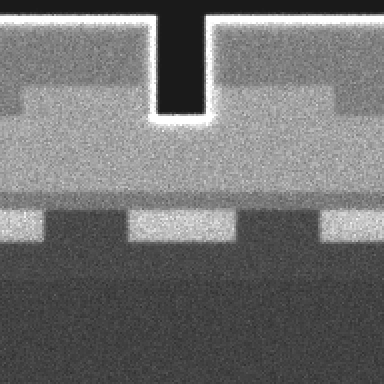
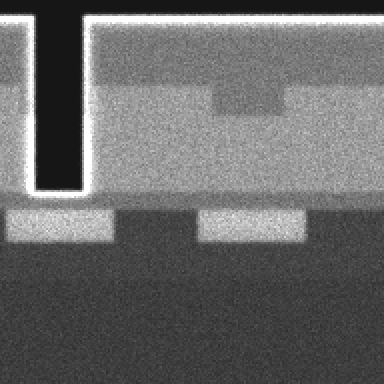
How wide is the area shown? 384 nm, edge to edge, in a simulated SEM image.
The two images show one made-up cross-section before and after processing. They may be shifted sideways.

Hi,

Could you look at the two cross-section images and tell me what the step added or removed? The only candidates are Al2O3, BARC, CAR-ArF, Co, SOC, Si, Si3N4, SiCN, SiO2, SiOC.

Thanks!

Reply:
removed SiO2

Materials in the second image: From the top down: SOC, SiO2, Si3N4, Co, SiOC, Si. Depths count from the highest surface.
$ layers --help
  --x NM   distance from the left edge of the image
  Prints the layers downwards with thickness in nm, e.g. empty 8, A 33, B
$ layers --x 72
empty 176, Si3N4 18, Co 32, SiOC 38, Si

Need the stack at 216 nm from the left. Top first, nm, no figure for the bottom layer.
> SOC 100, SiO2 76, Si3N4 18, Co 32, SiOC 38, Si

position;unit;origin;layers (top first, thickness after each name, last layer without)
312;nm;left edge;SOC 70, SiO2 106, Si3N4 18, SiOC 70, Si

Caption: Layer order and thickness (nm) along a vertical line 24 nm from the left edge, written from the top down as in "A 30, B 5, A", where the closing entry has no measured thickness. SOC 100, SiO2 76, Si3N4 18, Co 32, SiOC 38, Si